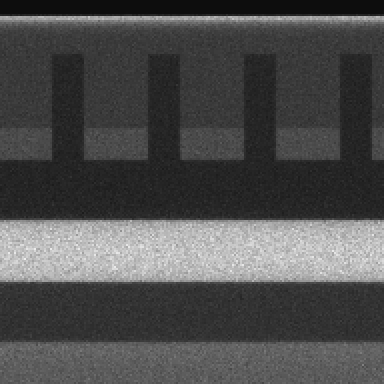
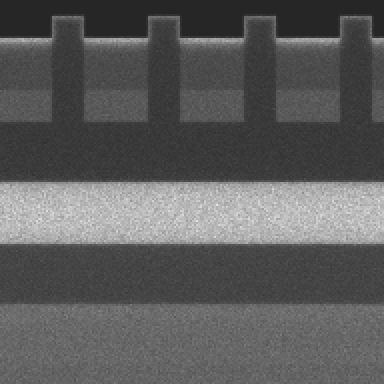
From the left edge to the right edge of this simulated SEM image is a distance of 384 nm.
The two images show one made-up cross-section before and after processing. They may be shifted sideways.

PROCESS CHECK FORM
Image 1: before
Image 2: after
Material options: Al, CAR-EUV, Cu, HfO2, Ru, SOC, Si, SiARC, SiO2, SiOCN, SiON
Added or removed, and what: removed, SOC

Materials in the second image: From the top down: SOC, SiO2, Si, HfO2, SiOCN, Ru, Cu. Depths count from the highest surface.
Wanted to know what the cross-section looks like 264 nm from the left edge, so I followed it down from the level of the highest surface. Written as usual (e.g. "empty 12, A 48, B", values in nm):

Si 166, HfO2 62, SiOCN 60, Ru 60, Cu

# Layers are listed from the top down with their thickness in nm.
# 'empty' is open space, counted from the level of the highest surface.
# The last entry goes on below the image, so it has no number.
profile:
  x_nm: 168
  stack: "Si 166, HfO2 62, SiOCN 60, Ru 60, Cu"